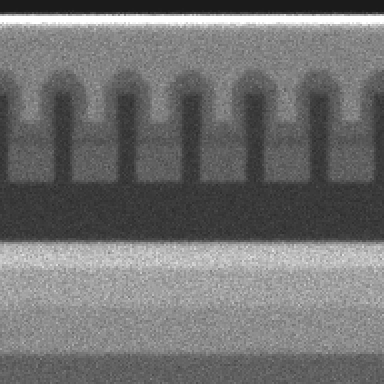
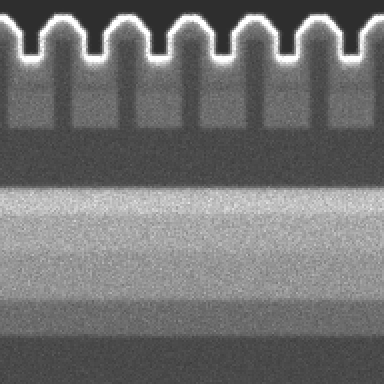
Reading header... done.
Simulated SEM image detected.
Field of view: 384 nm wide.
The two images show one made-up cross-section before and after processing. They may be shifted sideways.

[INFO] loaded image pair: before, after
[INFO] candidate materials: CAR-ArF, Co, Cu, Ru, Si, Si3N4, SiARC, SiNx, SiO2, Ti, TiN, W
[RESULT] removed SiO2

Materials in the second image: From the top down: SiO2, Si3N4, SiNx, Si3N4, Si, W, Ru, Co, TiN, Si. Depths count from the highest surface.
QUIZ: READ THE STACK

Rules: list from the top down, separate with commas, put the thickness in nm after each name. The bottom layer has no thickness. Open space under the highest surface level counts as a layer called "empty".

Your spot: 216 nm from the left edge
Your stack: empty 40, SiO2 12, Si3N4 14, SiNx 10, Si3N4 36, Si 60, W 26, Ru 38, Co 48, TiN 36, Si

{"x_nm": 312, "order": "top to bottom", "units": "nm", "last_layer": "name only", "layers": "Si3N4 14, SiNx 10, Si 148, W 26, Ru 38, Co 48, TiN 36, Si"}